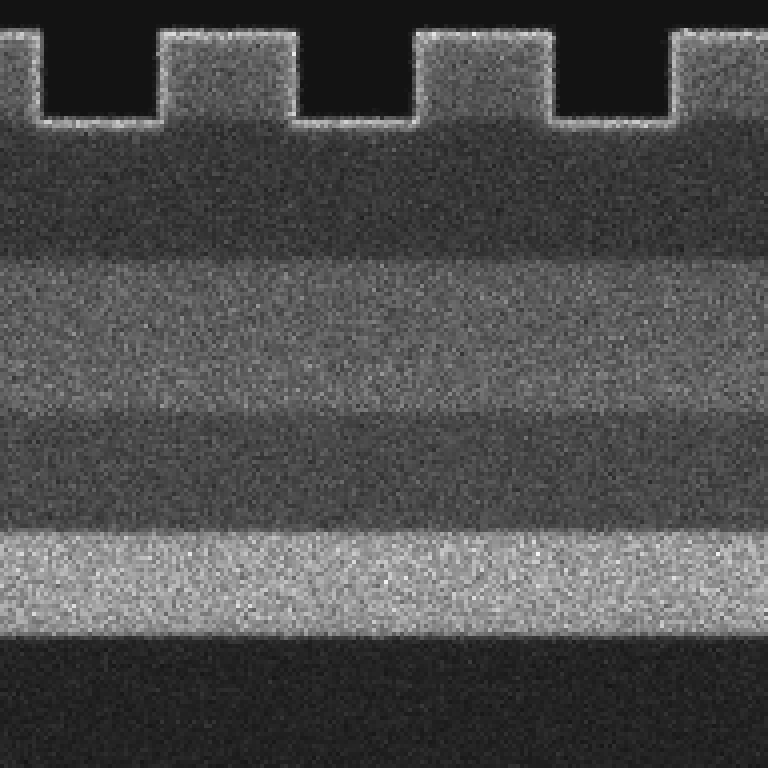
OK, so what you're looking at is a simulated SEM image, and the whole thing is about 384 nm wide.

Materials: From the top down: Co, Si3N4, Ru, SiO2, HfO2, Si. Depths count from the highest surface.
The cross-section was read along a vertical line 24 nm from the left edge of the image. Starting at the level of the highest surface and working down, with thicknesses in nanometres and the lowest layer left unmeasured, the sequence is empty 44, Si3N4 70, Ru 76, SiO2 60, HfO2 52, Si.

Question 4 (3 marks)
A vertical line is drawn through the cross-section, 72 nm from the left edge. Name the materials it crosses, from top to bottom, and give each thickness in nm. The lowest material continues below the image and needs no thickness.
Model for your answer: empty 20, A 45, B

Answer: empty 44, Si3N4 70, Ru 76, SiO2 60, HfO2 52, Si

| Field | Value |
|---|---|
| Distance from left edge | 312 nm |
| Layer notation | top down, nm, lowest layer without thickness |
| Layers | empty 44, Si3N4 70, Ru 76, SiO2 60, HfO2 52, Si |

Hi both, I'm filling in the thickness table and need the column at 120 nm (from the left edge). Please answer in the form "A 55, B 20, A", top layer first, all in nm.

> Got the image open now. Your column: Co 44, Si3N4 70, Ru 76, SiO2 60, HfO2 52, Si